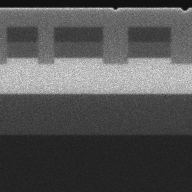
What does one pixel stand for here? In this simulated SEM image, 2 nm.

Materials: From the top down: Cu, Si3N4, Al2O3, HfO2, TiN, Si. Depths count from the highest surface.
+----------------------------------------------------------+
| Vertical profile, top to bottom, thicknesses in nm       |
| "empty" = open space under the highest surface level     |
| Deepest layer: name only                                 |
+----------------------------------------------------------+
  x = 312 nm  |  Cu 38, Si3N4 30, Al2O3 32, HfO2 72, TiN 82, Si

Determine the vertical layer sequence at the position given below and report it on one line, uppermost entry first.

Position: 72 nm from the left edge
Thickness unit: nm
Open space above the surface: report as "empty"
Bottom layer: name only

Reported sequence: Cu 38, Si3N4 30, Al2O3 32, HfO2 72, TiN 82, Si